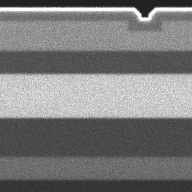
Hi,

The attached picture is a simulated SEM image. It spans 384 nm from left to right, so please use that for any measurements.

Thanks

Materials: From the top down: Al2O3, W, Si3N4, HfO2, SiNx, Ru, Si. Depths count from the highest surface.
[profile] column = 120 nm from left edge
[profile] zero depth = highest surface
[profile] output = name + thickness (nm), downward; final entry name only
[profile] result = Al2O3 26, W 60, Si3N4 46, HfO2 88, SiNx 78, Ru 46, Si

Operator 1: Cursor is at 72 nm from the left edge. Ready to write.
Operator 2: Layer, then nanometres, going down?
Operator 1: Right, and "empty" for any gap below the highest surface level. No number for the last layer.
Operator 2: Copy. Al2O3 26, W 60, Si3N4 46, HfO2 88, SiNx 78, Ru 46, Si